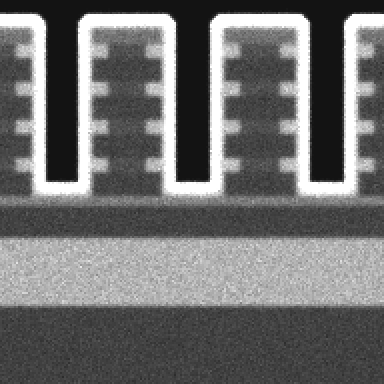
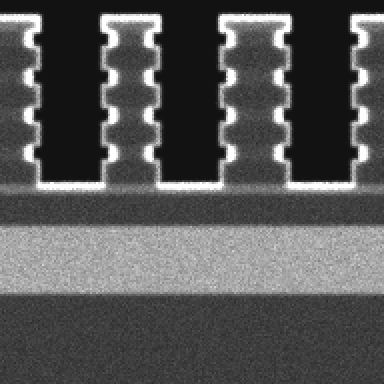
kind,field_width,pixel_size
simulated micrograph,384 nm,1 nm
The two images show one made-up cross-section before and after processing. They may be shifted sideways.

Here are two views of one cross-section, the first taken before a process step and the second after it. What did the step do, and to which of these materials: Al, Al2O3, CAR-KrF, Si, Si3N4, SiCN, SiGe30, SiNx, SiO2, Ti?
It removed Al2O3.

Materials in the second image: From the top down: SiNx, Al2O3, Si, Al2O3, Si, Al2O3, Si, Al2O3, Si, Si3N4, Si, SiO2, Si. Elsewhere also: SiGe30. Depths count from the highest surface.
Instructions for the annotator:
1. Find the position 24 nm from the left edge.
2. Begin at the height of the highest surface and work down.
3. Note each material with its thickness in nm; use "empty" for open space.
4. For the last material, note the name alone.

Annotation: SiNx 16, Al2O3 14, Si 24, Al2O3 14, Si 24, Al2O3 14, Si 24, Al2O3 14, Si 24, Si3N4 10, Si 32, SiO2 68, Si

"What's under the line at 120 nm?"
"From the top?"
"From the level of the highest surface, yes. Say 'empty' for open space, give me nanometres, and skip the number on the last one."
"SiNx 16, SiGe30 14, Si 24, SiGe30 14, Si 24, SiGe30 14, Si 24, SiGe30 14, Si 24, Si3N4 10, Si 32, SiO2 68, Si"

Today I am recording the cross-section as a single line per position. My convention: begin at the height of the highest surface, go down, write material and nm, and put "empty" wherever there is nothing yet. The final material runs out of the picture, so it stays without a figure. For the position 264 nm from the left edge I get SiNx 16, SiGe30 14, Si 24, SiGe30 14, Si 24, SiGe30 14, Si 24, SiGe30 14, Si 24, Si3N4 10, Si 32, SiO2 68, Si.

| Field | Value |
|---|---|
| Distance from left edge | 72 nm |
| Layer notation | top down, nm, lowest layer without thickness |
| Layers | empty 168, Si3N4 10, Si 32, SiO2 68, Si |